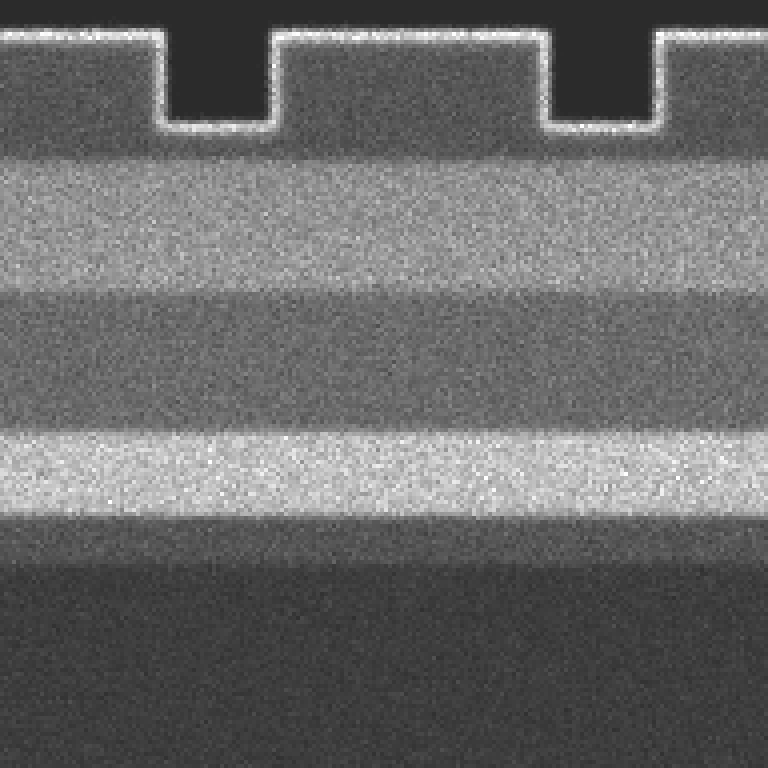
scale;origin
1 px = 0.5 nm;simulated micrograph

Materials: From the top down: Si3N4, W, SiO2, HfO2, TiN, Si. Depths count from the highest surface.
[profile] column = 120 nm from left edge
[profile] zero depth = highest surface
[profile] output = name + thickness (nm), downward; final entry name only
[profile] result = empty 46, Si3N4 18, W 66, SiO2 70, HfO2 42, TiN 24, Si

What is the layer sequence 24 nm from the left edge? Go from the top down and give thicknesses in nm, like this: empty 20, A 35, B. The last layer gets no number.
Si3N4 64, W 66, SiO2 70, HfO2 42, TiN 24, Si